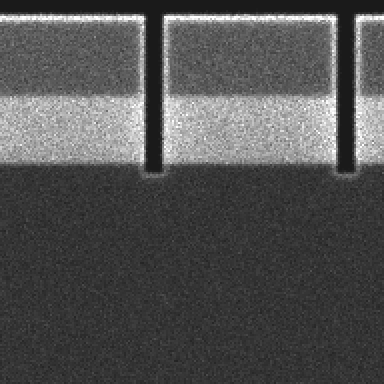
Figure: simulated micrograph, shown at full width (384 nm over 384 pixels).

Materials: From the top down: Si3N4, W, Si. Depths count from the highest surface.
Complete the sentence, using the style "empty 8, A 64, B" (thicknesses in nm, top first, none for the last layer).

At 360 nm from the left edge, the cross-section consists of Si3N4 80, W 68, Si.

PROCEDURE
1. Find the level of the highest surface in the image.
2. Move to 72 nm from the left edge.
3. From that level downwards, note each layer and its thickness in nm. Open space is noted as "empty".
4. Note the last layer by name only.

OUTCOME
Si3N4 80, W 68, Si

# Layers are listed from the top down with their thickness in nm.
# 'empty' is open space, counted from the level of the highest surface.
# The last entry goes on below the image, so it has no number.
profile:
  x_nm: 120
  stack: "Si3N4 80, W 68, Si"